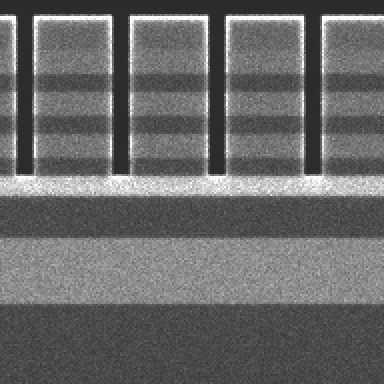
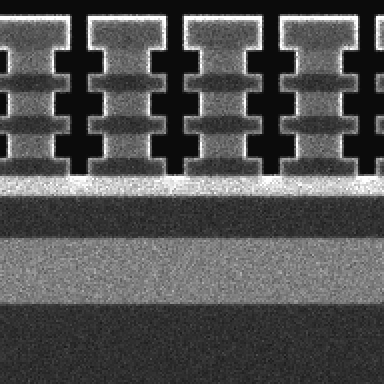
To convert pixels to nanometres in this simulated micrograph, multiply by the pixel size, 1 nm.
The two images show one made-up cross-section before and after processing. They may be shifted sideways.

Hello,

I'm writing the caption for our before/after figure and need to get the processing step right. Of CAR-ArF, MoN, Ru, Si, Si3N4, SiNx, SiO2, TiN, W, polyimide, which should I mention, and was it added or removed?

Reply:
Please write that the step removed TiN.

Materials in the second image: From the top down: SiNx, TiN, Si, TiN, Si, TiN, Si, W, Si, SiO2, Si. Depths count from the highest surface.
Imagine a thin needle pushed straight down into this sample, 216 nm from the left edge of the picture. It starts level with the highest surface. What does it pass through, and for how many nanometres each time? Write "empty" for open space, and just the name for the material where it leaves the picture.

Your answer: SiNx 34, TiN 24, Si 18, TiN 24, Si 18, TiN 24, Si 18, W 20, Si 42, SiO2 66, Si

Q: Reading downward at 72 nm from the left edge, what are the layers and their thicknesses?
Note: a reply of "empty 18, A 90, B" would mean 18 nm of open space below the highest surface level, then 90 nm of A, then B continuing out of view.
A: empty 160, W 20, Si 42, SiO2 66, Si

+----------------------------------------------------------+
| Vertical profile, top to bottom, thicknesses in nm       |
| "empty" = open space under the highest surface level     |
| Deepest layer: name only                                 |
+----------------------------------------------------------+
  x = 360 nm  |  empty 160, W 20, Si 42, SiO2 66, Si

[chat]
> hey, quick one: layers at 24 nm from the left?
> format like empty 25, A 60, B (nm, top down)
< SiNx 34, TiN 24, Si 18, TiN 24, Si 18, TiN 24, Si 18, W 20, Si 42, SiO2 66, Si